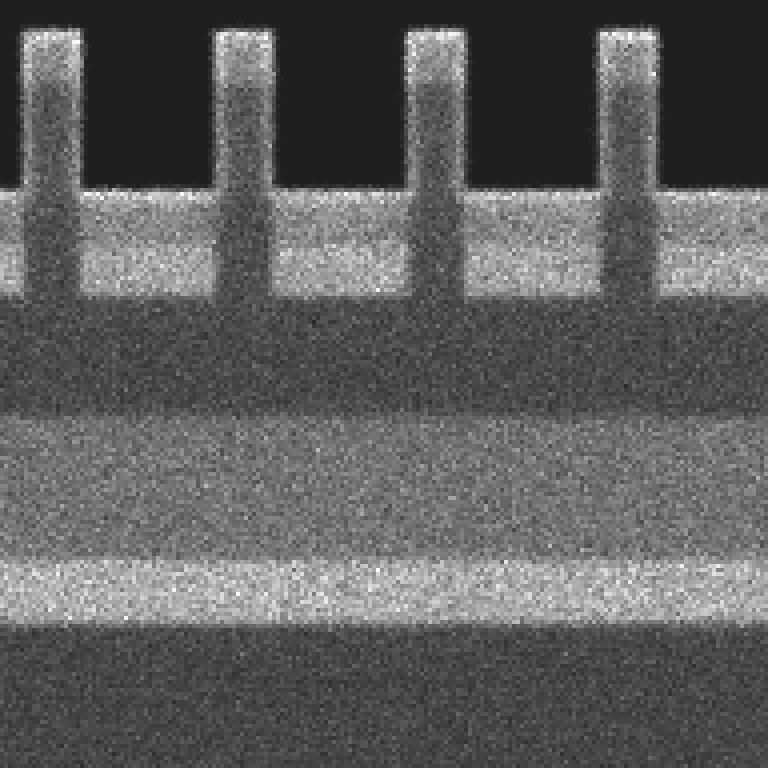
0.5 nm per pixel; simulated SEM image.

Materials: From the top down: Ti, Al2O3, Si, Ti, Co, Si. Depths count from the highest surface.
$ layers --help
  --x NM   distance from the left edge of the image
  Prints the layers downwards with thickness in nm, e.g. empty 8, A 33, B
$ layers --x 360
empty 80, Ti 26, Al2O3 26, Si 60, Ti 72, Co 32, Si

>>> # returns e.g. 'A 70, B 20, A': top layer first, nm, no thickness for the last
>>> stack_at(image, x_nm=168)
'empty 80, Ti 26, Al2O3 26, Si 60, Ti 72, Co 32, Si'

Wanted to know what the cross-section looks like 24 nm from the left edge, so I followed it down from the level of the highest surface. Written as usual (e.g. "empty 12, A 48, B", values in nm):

Ti 26, Si 166, Ti 72, Co 32, Si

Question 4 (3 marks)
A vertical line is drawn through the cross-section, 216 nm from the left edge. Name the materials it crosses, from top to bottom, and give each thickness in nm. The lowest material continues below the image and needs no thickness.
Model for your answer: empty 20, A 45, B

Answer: Ti 26, Si 166, Ti 72, Co 32, Si